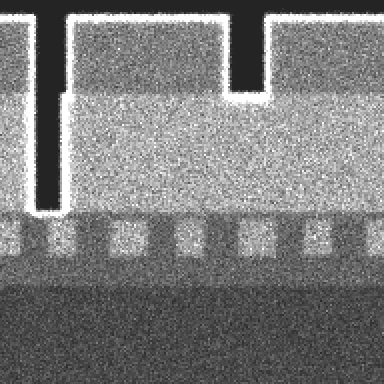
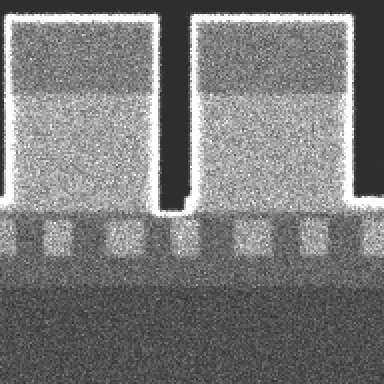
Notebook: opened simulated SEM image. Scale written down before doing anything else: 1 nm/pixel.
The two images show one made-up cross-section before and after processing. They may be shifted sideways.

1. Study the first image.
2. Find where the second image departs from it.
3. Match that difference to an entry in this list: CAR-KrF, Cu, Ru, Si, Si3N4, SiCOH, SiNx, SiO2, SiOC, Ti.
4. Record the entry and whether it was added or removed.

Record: SiO2 / removed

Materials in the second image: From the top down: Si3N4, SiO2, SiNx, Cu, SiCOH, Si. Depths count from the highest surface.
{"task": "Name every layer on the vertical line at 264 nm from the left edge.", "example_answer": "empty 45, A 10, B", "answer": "Si3N4 78, SiO2 118, SiNx 8, Cu 36, SiCOH 30, Si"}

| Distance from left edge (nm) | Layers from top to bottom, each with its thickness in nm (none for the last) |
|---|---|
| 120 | Si3N4 78, SiO2 118, SiNx 8, Cu 36, SiCOH 30, Si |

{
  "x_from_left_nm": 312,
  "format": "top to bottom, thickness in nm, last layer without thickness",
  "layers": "Si3N4 78, SiO2 118, SiNx 8, Cu 36, SiCOH 30, Si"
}